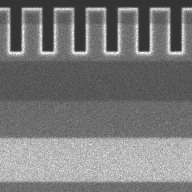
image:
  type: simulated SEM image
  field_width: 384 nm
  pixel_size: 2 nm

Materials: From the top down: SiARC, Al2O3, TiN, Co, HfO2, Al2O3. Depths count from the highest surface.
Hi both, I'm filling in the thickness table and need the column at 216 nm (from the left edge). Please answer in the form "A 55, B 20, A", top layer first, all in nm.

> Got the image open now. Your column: empty 88, Al2O3 18, TiN 80, Co 74, HfO2 88, Al2O3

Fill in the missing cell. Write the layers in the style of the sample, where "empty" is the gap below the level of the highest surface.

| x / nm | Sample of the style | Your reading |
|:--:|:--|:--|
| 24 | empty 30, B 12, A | empty 88, Al2O3 18, TiN 80, Co 74, HfO2 88, Al2O3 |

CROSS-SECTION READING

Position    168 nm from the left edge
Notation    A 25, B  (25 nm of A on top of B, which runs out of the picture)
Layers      empty 88, Al2O3 18, TiN 80, Co 74, HfO2 88, Al2O3